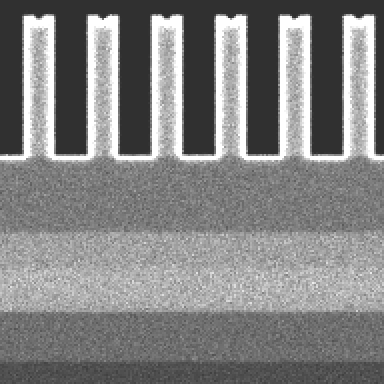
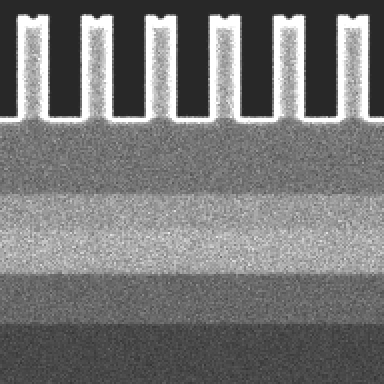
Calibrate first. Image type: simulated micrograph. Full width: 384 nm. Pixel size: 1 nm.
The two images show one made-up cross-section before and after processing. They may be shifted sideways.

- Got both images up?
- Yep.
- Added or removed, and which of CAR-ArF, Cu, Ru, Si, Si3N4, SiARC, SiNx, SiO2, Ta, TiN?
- removed, SiO2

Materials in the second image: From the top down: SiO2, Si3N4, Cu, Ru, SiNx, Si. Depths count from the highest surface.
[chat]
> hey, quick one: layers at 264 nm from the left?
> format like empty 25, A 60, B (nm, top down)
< empty 102, Si3N4 76, Cu 36, Ru 44, SiNx 50, Si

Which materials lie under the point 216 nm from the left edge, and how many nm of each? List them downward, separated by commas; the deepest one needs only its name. SiO2 102, Si3N4 76, Cu 36, Ru 44, SiNx 50, Si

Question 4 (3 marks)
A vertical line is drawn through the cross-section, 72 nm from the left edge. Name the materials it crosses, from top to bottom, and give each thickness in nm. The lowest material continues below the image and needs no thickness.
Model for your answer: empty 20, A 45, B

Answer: empty 102, Si3N4 76, Cu 36, Ru 44, SiNx 50, Si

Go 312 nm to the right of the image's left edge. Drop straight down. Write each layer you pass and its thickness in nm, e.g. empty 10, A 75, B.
empty 102, Si3N4 76, Cu 36, Ru 44, SiNx 50, Si